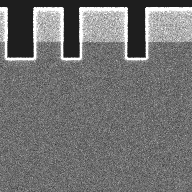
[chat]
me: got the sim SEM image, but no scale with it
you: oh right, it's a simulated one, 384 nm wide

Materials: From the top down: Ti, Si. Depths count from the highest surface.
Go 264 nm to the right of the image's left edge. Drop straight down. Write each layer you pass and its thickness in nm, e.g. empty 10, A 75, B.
empty 100, Si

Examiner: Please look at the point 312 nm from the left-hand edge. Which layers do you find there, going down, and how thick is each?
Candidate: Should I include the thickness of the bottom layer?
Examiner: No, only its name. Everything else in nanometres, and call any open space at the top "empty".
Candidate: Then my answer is Ti 68, Si